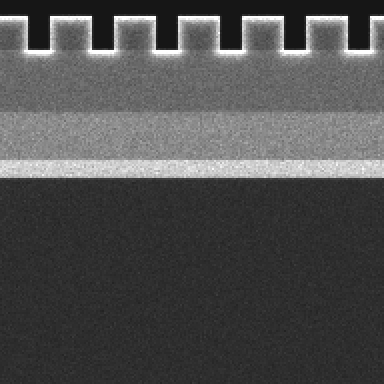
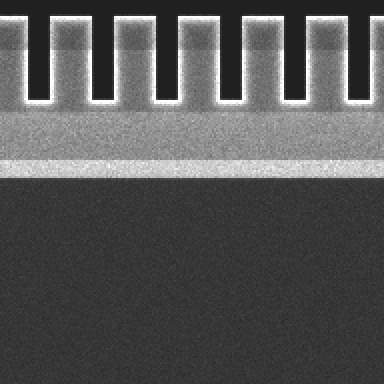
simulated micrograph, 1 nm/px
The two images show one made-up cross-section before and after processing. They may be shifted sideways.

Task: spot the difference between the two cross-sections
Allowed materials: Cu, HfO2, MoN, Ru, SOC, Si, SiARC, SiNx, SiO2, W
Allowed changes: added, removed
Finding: removed SiO2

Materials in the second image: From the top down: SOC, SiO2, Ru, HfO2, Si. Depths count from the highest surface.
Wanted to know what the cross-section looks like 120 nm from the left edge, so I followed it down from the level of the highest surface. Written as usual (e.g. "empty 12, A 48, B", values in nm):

SOC 34, SiO2 62, Ru 48, HfO2 18, Si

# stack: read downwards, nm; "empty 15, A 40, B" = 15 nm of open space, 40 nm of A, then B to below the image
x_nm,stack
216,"SOC 34, SiO2 62, Ru 48, HfO2 18, Si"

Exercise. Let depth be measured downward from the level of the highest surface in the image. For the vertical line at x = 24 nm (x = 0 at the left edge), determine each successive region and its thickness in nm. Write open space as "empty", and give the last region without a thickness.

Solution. SOC 34, SiO2 62, Ru 48, HfO2 18, Si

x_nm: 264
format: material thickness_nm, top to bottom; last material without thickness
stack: SOC 34, SiO2 62, Ru 48, HfO2 18, Si